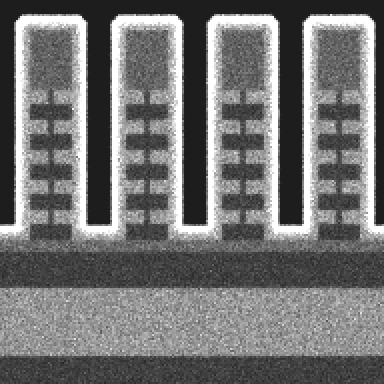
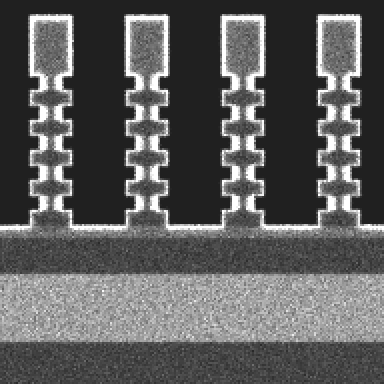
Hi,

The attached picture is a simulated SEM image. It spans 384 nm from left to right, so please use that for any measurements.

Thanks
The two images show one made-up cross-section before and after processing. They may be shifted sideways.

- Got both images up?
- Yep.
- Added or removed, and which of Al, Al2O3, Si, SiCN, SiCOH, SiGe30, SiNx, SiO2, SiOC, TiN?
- removed, Al2O3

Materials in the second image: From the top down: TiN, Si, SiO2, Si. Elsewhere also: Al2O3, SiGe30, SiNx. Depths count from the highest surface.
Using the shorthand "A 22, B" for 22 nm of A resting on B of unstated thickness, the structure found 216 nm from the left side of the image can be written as empty 210, TiN 12, Si 36, SiO2 68, Si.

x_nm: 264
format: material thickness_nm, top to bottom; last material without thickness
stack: empty 210, TiN 12, Si 36, SiO2 68, Si